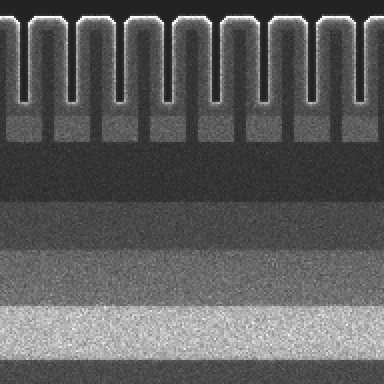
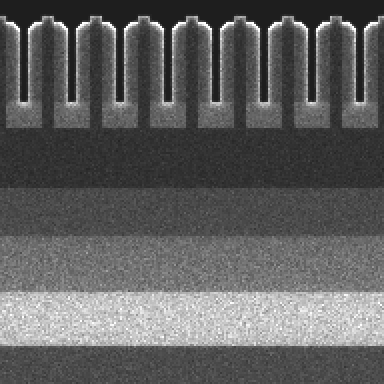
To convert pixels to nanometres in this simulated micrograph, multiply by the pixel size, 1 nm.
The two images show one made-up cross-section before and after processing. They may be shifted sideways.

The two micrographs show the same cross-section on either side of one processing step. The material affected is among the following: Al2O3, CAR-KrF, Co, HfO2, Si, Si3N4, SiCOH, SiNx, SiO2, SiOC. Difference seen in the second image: Si3N4 removed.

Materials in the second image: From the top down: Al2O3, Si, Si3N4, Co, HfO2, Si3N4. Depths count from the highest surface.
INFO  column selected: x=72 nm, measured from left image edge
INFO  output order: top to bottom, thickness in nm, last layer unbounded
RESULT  empty 86, Al2O3 26, Si 60, Si3N4 48, Co 56, HfO2 54, Si3N4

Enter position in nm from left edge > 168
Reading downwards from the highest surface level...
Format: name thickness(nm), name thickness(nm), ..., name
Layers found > empty 86, Al2O3 26, Si 60, Si3N4 48, Co 56, HfO2 54, Si3N4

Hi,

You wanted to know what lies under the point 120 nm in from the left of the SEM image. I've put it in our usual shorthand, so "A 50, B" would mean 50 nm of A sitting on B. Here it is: empty 86, Al2O3 26, Si 60, Si3N4 48, Co 56, HfO2 54, Si3N4